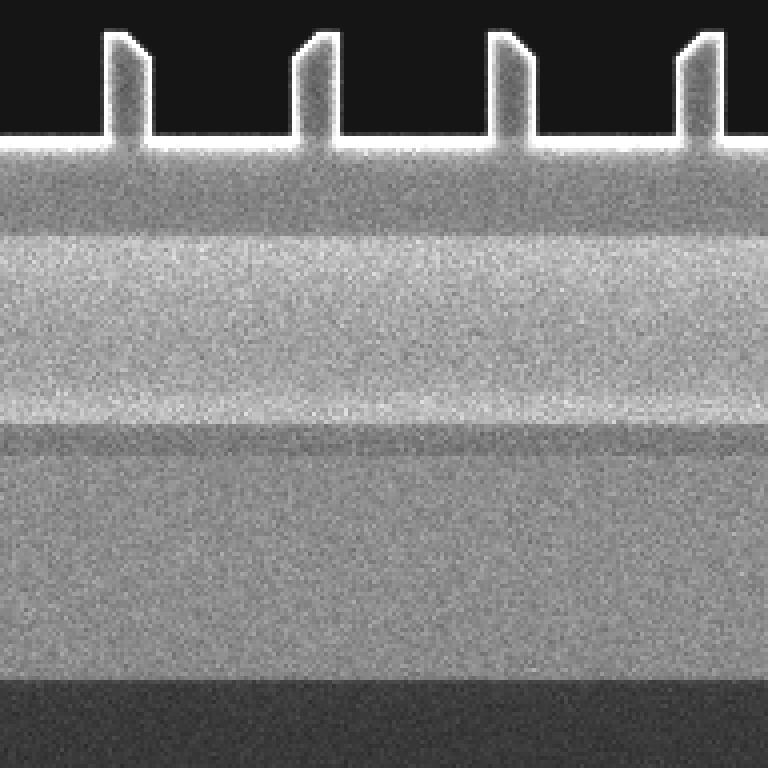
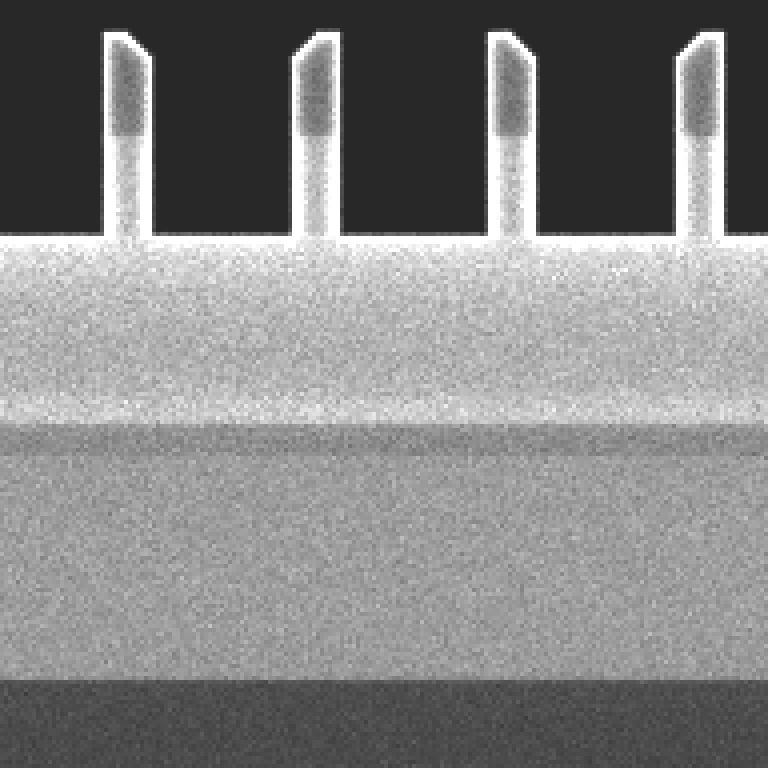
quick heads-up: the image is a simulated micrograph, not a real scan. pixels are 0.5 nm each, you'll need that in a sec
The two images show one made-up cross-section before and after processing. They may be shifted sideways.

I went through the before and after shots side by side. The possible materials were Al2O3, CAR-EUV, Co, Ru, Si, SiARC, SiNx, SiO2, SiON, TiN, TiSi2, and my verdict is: removed, SiO2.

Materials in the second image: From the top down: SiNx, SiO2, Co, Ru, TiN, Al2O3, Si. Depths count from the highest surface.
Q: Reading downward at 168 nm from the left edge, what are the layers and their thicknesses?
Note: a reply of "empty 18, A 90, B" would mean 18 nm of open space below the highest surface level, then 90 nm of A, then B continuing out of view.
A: SiNx 52, SiO2 50, Co 80, Ru 14, TiN 16, Al2O3 112, Si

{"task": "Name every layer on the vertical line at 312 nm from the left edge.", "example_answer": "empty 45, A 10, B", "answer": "empty 102, Co 80, Ru 14, TiN 16, Al2O3 112, Si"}